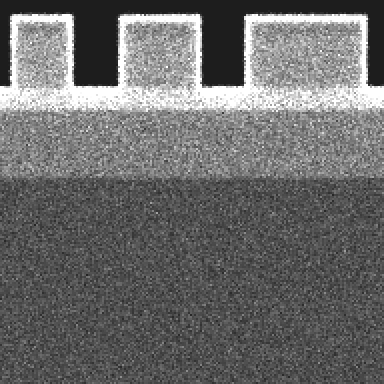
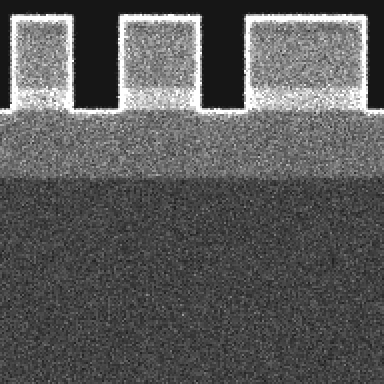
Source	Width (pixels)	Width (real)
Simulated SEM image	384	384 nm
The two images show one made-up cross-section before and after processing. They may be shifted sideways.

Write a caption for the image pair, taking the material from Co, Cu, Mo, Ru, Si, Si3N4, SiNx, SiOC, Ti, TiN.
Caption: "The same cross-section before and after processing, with Co removed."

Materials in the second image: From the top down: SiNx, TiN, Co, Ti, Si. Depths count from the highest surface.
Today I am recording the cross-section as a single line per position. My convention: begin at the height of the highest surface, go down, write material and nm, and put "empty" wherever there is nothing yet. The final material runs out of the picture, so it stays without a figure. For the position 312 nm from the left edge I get SiNx 18, TiN 54, Co 22, Ti 68, Si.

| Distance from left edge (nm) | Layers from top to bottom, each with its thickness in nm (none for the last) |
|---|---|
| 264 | SiNx 18, TiN 54, Co 22, Ti 68, Si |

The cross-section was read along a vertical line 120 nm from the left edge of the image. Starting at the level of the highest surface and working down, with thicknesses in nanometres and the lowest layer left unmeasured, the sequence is SiNx 18, TiN 54, Co 22, Ti 68, Si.